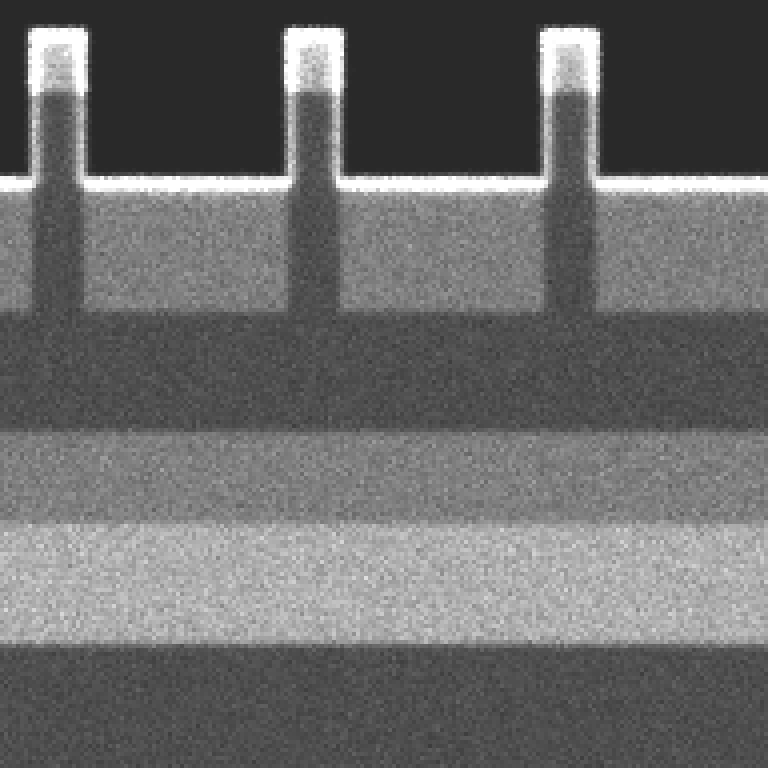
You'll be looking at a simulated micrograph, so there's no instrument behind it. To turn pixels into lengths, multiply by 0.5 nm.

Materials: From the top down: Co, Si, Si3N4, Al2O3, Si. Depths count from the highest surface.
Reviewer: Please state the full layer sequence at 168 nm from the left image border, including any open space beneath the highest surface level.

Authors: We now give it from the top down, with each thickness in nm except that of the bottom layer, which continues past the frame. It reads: Co 30, Si 170, Si3N4 46, Al2O3 60, Si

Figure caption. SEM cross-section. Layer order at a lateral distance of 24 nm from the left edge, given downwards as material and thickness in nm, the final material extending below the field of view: Co 30, Si 170, Si3N4 46, Al2O3 60, Si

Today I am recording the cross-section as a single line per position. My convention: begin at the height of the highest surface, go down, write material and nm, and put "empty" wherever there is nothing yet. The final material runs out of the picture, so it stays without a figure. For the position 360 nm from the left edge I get empty 74, Si3N4 66, Si 60, Si3N4 46, Al2O3 60, Si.